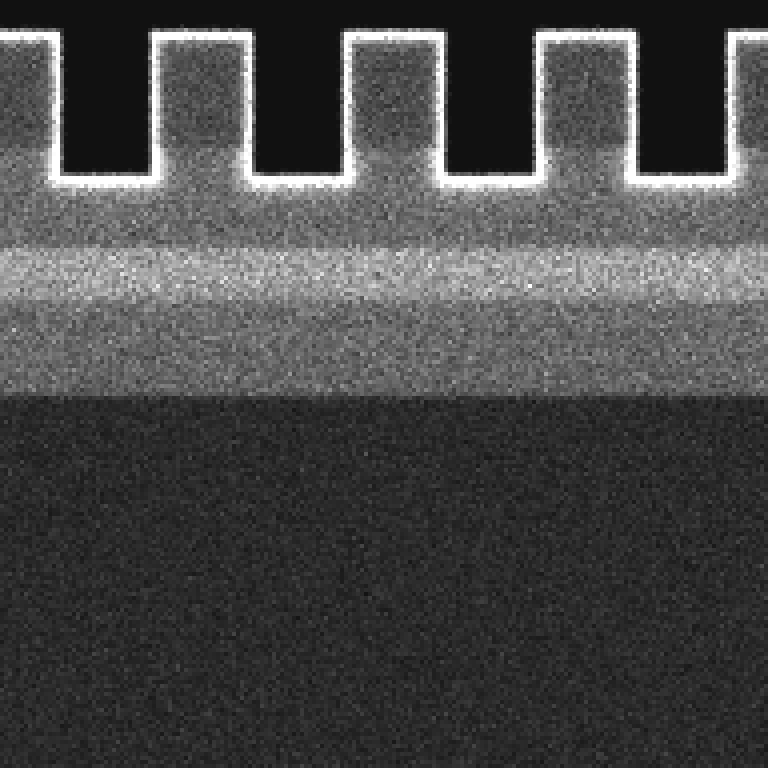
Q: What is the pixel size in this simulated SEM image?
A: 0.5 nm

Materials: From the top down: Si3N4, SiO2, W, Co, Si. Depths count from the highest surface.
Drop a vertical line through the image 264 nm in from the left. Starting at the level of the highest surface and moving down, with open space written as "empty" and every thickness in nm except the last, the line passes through empty 72, SiO2 36, W 26, Co 48, Si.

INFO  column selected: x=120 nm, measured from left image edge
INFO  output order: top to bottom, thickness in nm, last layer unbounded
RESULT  Si3N4 58, SiO2 50, W 26, Co 48, Si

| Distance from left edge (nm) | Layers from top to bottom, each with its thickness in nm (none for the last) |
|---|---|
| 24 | Si3N4 58, SiO2 50, W 26, Co 48, Si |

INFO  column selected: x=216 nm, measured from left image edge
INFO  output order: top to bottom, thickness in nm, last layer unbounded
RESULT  Si3N4 58, SiO2 50, W 26, Co 48, Si